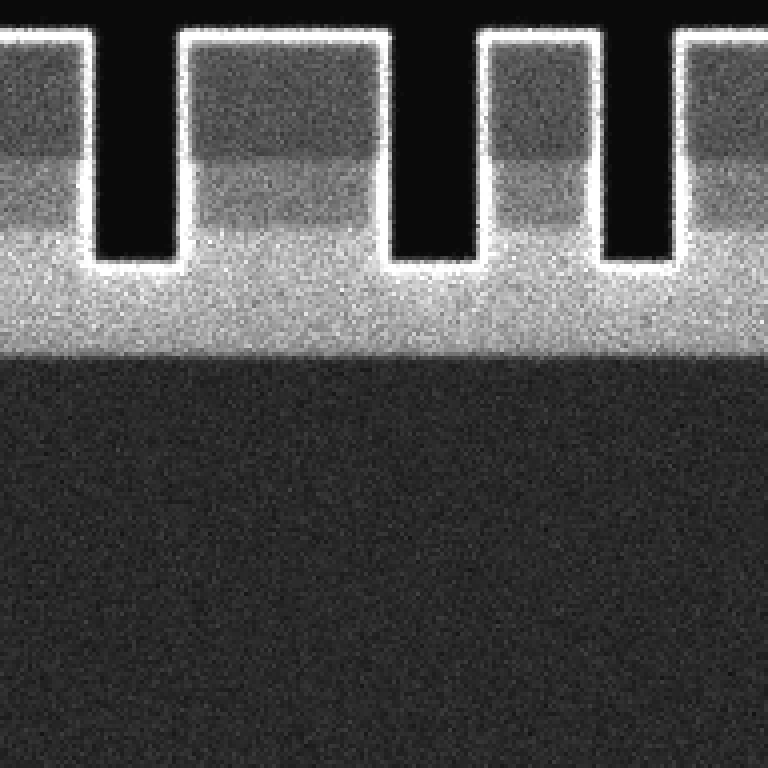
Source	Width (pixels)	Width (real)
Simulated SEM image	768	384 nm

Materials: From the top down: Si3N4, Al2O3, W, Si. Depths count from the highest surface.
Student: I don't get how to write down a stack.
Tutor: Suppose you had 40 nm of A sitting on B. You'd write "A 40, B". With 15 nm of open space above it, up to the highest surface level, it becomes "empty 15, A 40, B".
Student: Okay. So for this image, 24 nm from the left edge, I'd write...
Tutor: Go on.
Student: Si3N4 64, Al2O3 34, W 64, Si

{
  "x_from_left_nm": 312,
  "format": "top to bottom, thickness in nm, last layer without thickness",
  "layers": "empty 116, W 46, Si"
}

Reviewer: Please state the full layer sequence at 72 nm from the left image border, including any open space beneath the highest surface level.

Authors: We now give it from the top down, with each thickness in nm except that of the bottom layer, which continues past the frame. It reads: empty 116, W 46, Si